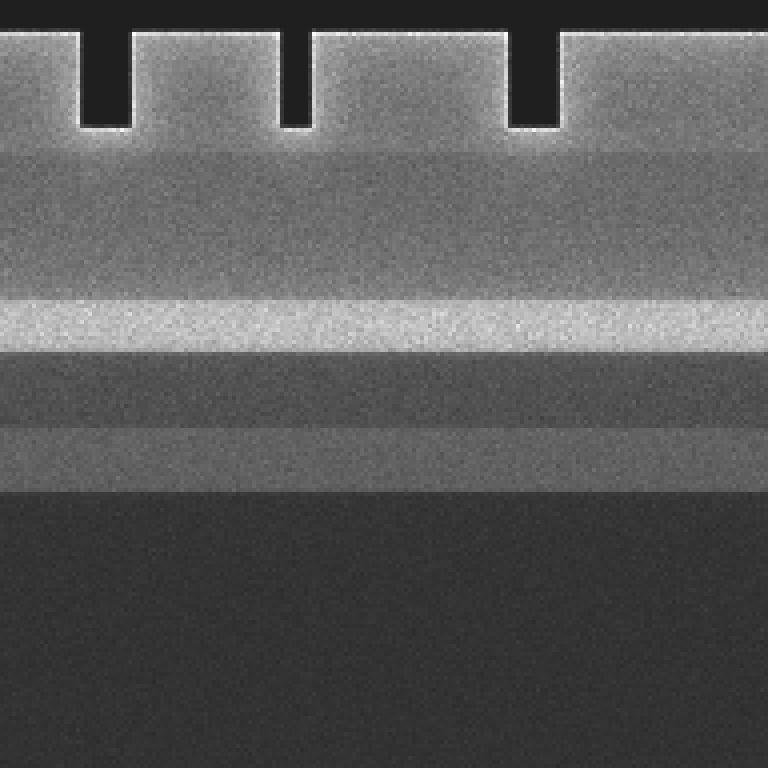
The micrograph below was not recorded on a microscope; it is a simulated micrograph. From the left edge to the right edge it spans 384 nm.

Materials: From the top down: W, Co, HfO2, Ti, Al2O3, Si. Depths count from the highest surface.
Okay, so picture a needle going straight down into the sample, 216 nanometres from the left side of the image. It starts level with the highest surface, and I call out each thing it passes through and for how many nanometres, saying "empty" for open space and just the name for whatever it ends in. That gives W 60, Co 74, HfO2 26, Ti 38, Al2O3 32, Si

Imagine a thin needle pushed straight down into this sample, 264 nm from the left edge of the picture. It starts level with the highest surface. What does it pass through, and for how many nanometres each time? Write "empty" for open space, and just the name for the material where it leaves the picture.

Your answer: empty 48, W 12, Co 74, HfO2 26, Ti 38, Al2O3 32, Si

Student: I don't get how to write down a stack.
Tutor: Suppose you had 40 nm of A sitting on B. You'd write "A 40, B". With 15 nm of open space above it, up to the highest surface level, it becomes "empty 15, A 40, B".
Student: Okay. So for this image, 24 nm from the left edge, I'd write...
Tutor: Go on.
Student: W 60, Co 74, HfO2 26, Ti 38, Al2O3 32, Si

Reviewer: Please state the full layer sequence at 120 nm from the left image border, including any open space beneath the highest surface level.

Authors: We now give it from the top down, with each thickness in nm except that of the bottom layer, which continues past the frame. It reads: W 60, Co 74, HfO2 26, Ti 38, Al2O3 32, Si